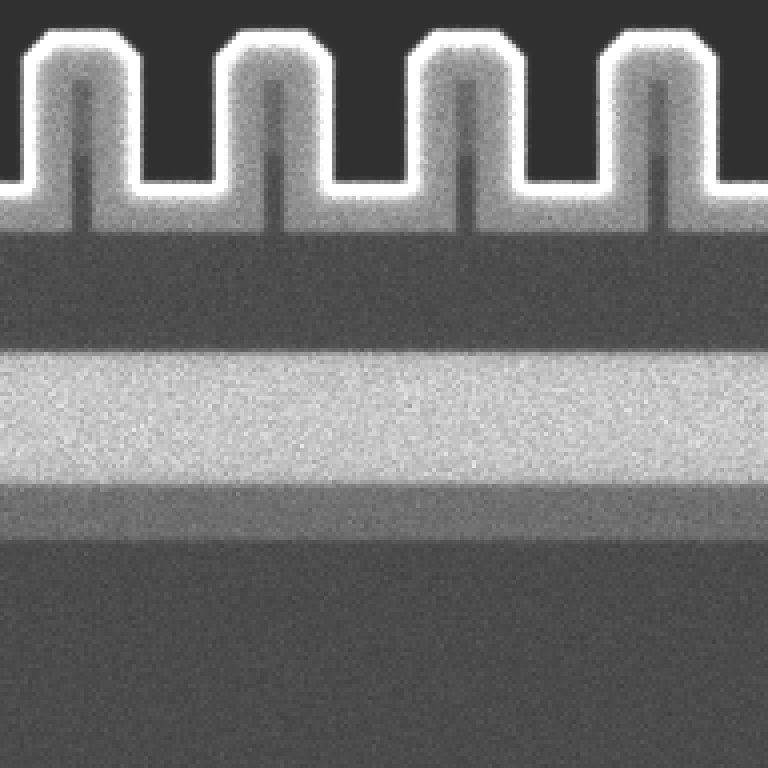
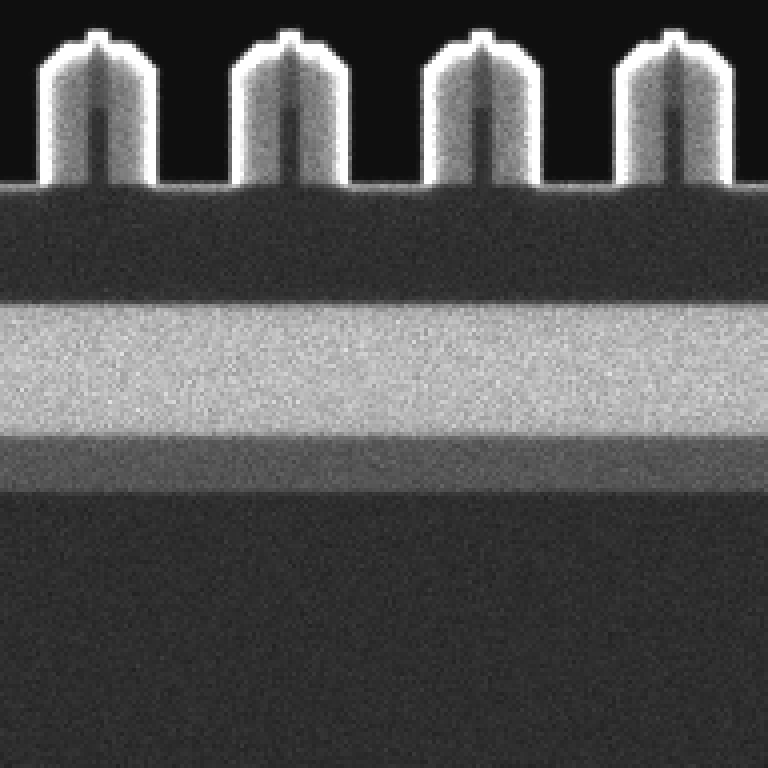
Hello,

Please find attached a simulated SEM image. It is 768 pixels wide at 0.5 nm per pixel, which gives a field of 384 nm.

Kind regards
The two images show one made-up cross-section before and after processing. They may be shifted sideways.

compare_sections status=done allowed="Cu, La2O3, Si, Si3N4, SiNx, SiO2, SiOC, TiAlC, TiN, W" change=removed material="SiO2"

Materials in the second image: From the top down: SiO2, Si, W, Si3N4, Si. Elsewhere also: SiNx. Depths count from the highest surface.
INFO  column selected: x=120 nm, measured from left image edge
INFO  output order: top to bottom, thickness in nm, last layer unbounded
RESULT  empty 14, SiO2 62, Si 60, W 66, Si3N4 28, Si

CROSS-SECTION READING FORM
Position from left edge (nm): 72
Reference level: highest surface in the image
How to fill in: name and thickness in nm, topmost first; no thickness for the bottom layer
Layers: empty 14, SiO2 62, Si 60, W 66, Si3N4 28, Si